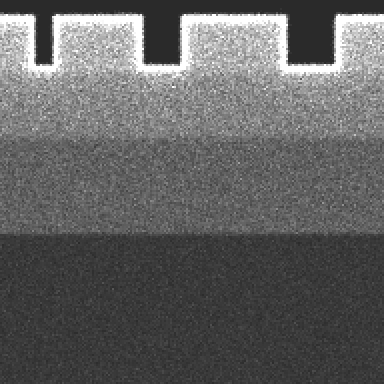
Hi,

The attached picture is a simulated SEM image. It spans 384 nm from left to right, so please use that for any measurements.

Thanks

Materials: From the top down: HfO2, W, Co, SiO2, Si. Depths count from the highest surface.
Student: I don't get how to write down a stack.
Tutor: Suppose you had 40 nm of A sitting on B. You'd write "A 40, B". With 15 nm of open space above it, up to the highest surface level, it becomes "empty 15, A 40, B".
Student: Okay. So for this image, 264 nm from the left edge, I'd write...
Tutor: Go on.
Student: HfO2 56, W 66, Co 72, SiO2 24, Si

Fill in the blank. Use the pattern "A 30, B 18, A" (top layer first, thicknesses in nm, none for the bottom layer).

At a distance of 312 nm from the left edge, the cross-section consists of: empty 50, HfO2 6, W 66, Co 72, SiO2 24, Si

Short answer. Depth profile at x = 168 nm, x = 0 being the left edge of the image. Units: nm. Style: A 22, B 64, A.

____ empty 50, HfO2 6, W 66, Co 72, SiO2 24, Si